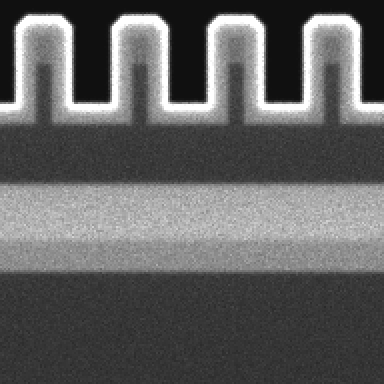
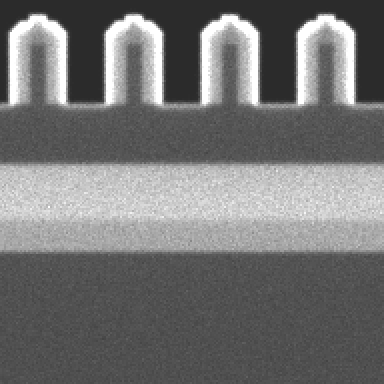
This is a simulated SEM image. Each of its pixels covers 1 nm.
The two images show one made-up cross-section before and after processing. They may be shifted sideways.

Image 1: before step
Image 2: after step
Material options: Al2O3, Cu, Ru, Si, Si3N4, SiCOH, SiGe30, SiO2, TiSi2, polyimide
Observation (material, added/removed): SiO2, removed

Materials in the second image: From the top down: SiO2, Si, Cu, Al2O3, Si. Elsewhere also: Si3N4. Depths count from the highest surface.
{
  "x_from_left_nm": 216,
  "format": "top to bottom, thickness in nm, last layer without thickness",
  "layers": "empty 6, SiO2 82, Si 60, Cu 56, Al2O3 32, Si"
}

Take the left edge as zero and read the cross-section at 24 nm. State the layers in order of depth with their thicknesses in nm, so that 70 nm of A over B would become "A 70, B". empty 6, SiO2 82, Si 60, Cu 56, Al2O3 32, Si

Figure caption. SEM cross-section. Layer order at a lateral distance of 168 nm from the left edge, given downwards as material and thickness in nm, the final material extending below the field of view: empty 88, Si 60, Cu 56, Al2O3 32, Si